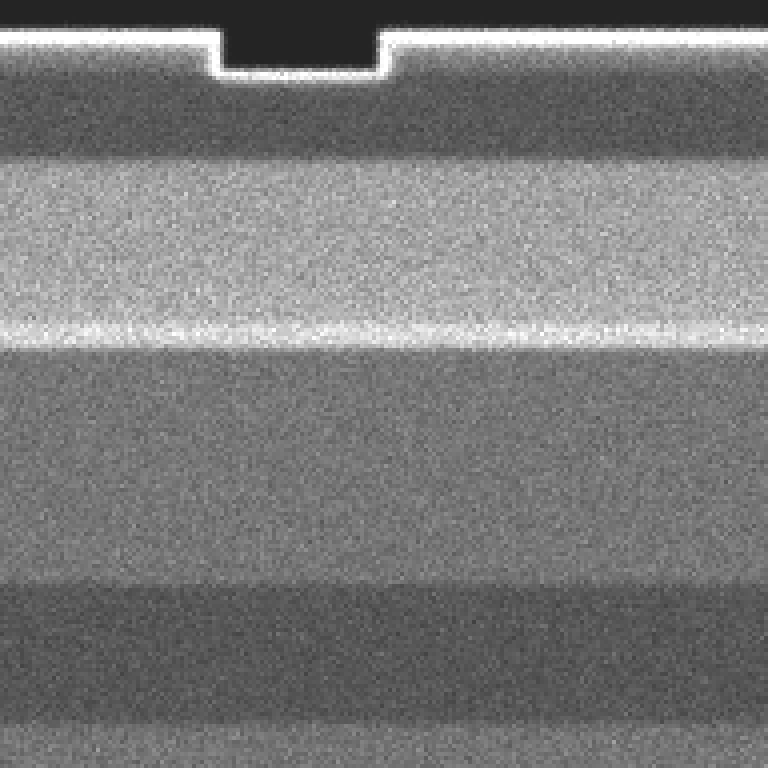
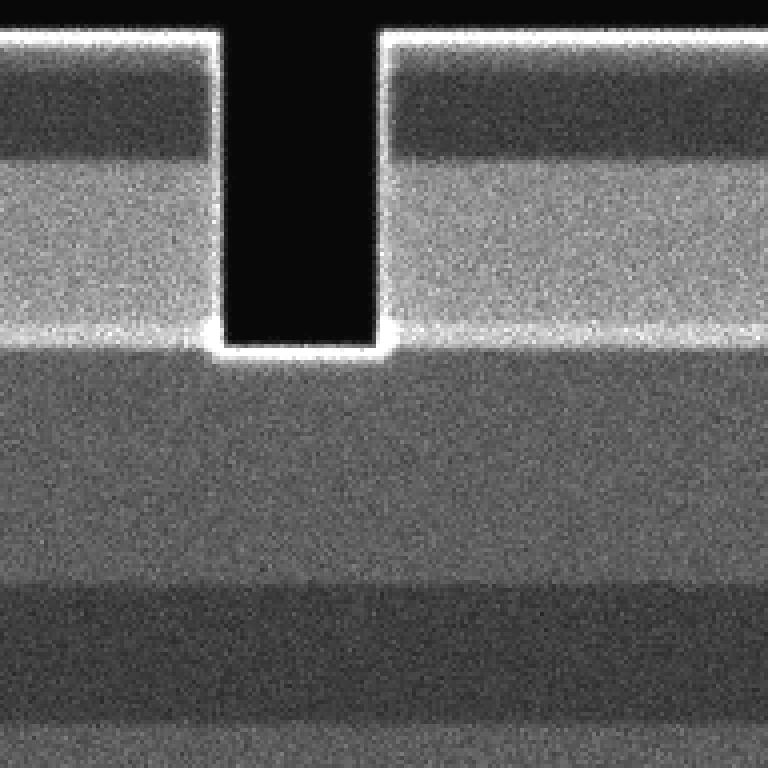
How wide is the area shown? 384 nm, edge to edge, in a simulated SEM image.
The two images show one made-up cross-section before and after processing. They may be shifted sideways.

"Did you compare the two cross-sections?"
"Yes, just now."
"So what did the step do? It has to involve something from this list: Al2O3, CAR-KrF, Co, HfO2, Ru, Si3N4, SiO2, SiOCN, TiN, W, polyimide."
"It removed HfO2 and Si3N4 and W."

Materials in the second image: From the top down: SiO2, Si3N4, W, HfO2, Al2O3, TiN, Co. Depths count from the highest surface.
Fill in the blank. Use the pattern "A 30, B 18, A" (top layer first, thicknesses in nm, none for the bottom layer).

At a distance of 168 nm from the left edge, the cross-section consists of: empty 158, Al2O3 118, TiN 70, Co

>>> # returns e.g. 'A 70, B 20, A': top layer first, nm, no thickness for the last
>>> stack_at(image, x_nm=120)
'empty 158, Al2O3 118, TiN 70, Co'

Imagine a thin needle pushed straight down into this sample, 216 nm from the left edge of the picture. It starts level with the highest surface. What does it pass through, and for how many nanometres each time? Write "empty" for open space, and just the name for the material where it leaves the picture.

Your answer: SiO2 20, Si3N4 44, W 82, HfO2 12, Al2O3 118, TiN 70, Co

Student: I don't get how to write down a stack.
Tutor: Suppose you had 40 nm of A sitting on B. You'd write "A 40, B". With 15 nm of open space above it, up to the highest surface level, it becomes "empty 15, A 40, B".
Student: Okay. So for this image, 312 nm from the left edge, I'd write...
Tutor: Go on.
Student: SiO2 20, Si3N4 44, W 82, HfO2 12, Al2O3 118, TiN 70, Co